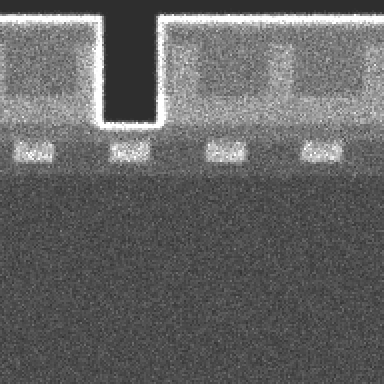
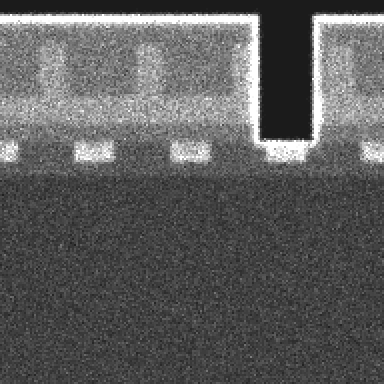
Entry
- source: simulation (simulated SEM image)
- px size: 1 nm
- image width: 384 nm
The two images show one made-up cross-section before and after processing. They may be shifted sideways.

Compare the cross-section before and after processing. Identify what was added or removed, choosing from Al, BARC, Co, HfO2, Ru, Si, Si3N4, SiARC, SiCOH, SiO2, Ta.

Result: Si3N4 removed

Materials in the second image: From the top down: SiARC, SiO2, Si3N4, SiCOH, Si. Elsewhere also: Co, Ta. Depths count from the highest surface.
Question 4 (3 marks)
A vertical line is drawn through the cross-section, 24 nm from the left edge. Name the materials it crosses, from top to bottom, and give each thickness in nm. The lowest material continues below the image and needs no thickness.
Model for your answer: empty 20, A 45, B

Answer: SiARC 80, SiO2 28, Si3N4 18, SiCOH 34, Si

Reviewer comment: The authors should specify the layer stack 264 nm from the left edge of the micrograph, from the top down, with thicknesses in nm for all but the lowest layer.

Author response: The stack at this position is empty 126, SiCOH 34, Si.